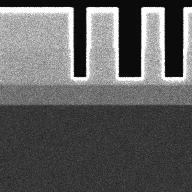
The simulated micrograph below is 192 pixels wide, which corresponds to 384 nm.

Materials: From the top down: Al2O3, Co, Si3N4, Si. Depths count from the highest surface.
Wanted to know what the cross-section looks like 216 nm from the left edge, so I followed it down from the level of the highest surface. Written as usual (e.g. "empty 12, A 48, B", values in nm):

Al2O3 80, Co 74, Si3N4 40, Si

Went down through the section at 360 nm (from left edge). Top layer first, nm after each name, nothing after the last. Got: empty 140, Co 14, Si3N4 40, Si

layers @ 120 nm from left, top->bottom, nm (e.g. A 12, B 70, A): Al2O3 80, Co 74, Si3N4 40, Si